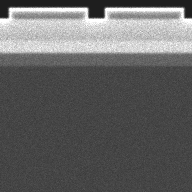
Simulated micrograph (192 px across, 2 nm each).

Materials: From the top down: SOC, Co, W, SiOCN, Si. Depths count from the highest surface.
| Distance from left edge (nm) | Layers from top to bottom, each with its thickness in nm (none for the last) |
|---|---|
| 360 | SOC 22, Co 44, W 24, SiOCN 26, Si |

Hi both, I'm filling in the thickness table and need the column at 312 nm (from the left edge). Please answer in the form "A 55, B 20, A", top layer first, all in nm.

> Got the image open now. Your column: SOC 22, Co 44, W 24, SiOCN 26, Si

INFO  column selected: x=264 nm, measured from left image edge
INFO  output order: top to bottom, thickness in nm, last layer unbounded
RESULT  SOC 22, Co 44, W 24, SiOCN 26, Si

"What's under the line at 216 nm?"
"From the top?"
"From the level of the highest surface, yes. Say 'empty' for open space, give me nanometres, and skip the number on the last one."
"SOC 22, Co 44, W 24, SiOCN 26, Si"